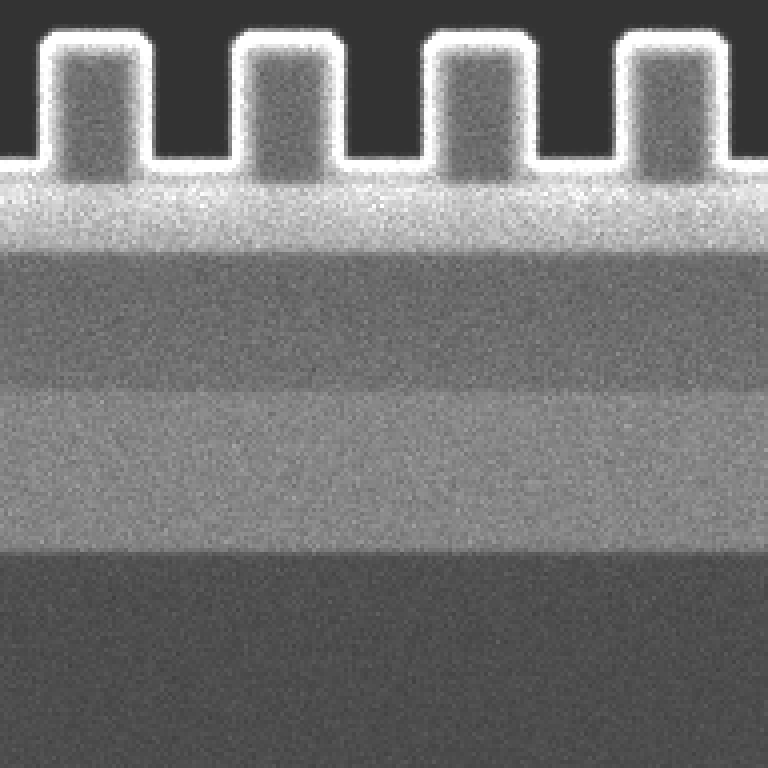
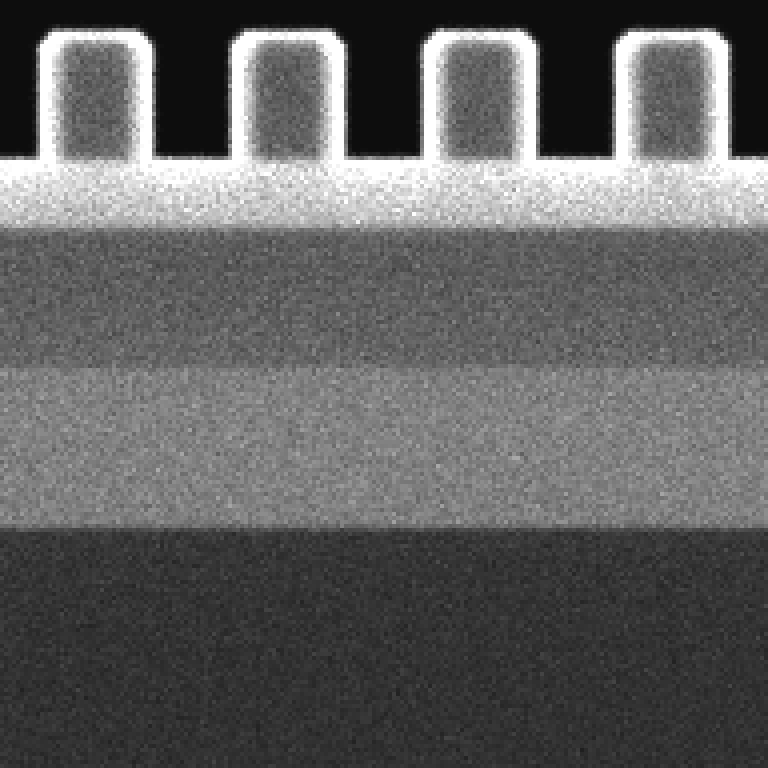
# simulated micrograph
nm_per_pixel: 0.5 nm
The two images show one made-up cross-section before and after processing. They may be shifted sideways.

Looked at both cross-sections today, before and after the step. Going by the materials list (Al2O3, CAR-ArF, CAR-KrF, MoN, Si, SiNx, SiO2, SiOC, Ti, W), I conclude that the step removed Al2O3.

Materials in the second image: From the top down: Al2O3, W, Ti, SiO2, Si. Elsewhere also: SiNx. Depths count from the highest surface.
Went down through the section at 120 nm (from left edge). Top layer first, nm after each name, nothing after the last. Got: empty 2, Al2O3 62, W 34, Ti 70, SiO2 80, Si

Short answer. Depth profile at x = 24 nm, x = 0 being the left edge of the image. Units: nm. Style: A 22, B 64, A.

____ empty 2, Al2O3 62, W 34, Ti 70, SiO2 80, Si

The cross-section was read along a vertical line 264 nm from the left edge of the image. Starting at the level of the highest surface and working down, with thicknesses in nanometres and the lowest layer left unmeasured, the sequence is empty 4, Al2O3 60, W 34, Ti 70, SiO2 80, Si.